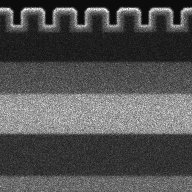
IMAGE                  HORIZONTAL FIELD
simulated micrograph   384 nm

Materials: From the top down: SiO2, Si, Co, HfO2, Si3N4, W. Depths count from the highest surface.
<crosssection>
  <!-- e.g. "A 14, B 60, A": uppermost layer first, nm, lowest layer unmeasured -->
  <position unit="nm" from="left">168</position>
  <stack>empty 34, SiO2 14, Si 60, Co 64, HfO2 80, Si3N4 84, W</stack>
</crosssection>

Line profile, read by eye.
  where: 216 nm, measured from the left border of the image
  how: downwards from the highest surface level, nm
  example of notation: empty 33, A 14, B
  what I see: empty 6, SiO2 42, Si 60, Co 64, HfO2 80, Si3N4 84, W